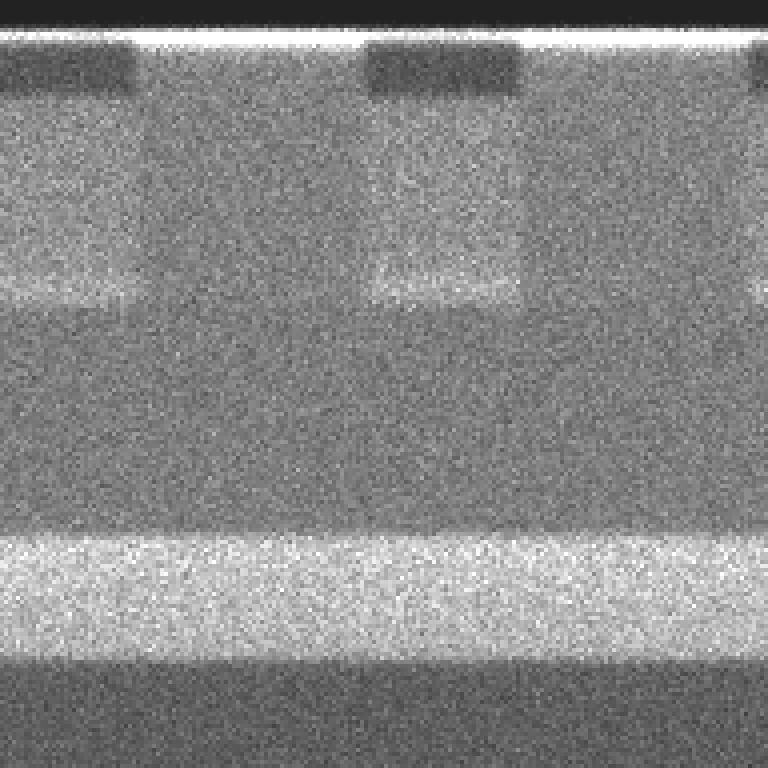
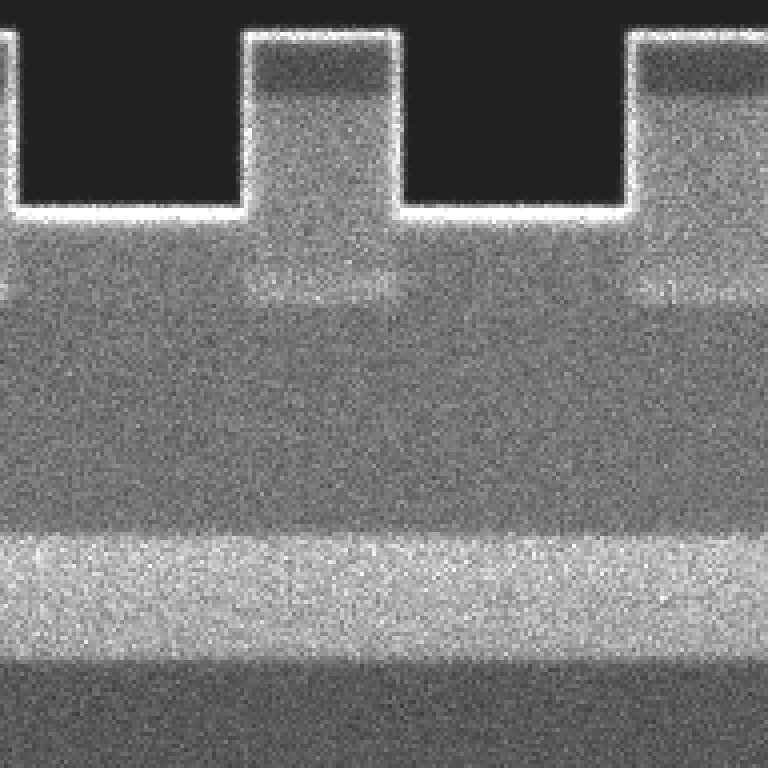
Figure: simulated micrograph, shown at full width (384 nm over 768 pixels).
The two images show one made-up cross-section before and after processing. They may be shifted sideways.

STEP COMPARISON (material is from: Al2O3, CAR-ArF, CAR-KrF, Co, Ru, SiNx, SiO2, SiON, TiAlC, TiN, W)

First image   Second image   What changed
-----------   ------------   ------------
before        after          Al2O3, removed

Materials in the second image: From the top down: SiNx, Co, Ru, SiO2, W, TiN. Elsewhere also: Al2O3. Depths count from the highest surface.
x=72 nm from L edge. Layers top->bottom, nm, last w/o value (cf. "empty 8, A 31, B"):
empty 88, Al2O3 48, SiO2 116, W 62, TiN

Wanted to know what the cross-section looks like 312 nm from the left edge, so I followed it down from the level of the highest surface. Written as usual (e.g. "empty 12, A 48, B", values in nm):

empty 88, Al2O3 48, SiO2 116, W 62, TiN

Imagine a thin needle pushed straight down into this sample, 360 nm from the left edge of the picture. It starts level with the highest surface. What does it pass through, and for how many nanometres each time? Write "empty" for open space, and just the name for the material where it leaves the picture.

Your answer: SiNx 32, Co 90, Ru 14, SiO2 116, W 62, TiN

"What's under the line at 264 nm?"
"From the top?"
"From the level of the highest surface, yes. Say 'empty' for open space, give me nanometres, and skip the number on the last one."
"empty 88, Al2O3 48, SiO2 116, W 62, TiN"